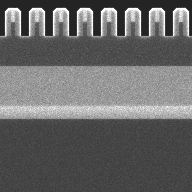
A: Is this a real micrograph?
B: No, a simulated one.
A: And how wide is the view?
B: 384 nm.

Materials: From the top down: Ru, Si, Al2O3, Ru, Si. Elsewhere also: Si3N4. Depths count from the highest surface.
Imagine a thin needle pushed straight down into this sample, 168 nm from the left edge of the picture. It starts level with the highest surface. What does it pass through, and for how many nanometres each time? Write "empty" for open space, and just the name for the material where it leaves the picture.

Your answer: Ru 28, Si 88, Al2O3 80, Ru 26, Si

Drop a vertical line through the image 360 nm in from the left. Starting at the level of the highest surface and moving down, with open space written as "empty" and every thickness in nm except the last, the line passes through Ru 28, Si 88, Al2O3 80, Ru 26, Si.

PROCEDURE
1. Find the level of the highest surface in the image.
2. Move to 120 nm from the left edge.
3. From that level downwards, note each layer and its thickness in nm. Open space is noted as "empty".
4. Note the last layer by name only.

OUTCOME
Ru 28, Si 88, Al2O3 80, Ru 26, Si